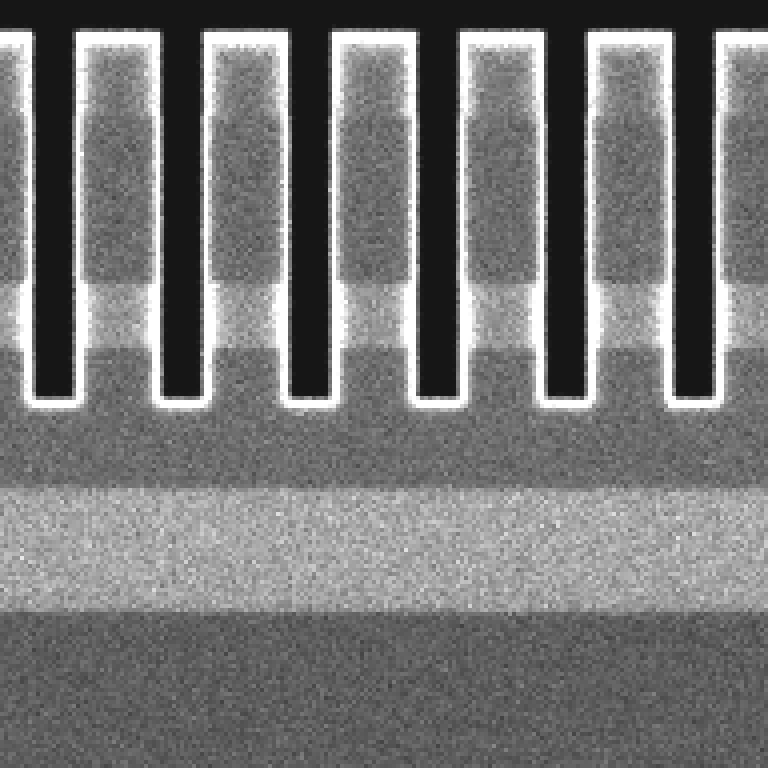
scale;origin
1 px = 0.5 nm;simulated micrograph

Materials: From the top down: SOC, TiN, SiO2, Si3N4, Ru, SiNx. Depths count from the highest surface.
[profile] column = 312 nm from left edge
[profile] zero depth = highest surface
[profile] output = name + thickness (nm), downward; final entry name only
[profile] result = SOC 42, TiN 84, SiO2 32, Si3N4 70, Ru 62, SiNx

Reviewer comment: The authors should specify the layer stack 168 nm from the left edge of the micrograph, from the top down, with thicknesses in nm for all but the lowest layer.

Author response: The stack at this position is SOC 42, TiN 84, SiO2 32, Si3N4 70, Ru 62, SiNx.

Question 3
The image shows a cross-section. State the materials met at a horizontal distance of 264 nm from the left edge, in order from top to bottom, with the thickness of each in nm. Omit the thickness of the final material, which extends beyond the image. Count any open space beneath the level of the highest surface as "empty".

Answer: SOC 42, TiN 84, SiO2 32, Si3N4 70, Ru 62, SiNx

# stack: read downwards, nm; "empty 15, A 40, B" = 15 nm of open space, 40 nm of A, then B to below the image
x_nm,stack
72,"SOC 42, TiN 84, SiO2 32, Si3N4 70, Ru 62, SiNx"